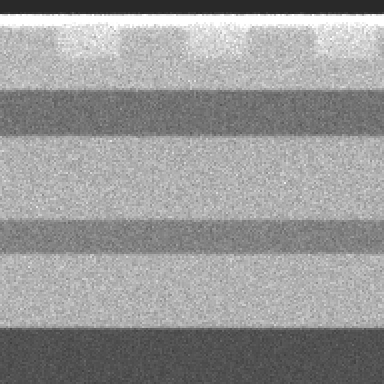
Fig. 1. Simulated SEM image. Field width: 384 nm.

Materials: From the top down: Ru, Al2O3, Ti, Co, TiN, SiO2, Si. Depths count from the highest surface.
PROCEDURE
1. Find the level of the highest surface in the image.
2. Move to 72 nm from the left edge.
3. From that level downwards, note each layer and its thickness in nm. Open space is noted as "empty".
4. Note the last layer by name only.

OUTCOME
Ru 42, Al2O3 32, Ti 46, Co 84, TiN 34, SiO2 74, Si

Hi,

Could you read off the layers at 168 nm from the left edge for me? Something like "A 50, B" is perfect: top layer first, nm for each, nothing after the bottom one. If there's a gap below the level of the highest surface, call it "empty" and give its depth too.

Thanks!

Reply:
Al2O3 74, Ti 46, Co 84, TiN 34, SiO2 74, Si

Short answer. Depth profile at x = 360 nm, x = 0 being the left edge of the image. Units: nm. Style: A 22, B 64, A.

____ Ru 42, Al2O3 32, Ti 46, Co 84, TiN 34, SiO2 74, Si